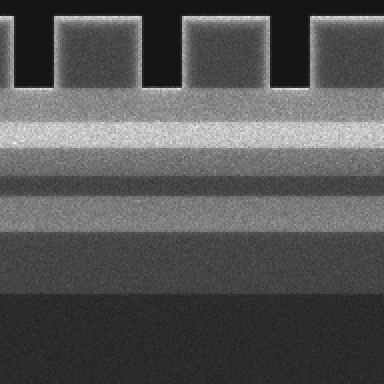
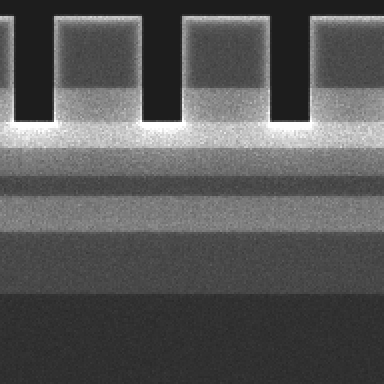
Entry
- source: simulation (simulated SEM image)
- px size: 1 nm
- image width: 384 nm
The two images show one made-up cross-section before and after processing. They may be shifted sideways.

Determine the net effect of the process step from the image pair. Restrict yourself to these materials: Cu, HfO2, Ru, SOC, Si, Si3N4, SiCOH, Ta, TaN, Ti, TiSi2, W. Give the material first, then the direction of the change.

Ru: removed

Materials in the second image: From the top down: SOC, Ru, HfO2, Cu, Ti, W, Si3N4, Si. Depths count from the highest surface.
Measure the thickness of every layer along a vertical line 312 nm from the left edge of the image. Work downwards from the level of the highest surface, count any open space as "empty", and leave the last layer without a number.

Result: SOC 72, Ru 34, HfO2 26, Cu 28, Ti 20, W 36, Si3N4 62, Si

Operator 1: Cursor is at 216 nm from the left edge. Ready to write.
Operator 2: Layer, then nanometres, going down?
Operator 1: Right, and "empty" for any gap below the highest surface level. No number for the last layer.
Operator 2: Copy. SOC 72, Ru 34, HfO2 26, Cu 28, Ti 20, W 36, Si3N4 62, Si